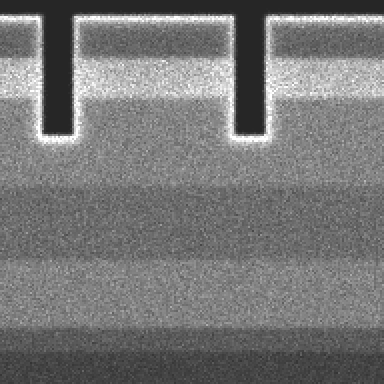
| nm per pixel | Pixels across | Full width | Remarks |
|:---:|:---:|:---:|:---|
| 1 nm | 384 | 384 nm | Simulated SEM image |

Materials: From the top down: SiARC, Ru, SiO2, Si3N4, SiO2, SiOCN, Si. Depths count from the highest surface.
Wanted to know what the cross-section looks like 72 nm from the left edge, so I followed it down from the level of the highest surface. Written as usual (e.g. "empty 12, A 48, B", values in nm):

empty 120, SiO2 50, Si3N4 74, SiO2 68, SiOCN 24, Si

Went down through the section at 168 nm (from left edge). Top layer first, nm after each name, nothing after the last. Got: SiARC 42, Ru 40, SiO2 88, Si3N4 74, SiO2 68, SiOCN 24, Si